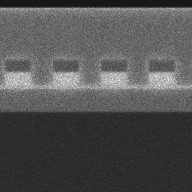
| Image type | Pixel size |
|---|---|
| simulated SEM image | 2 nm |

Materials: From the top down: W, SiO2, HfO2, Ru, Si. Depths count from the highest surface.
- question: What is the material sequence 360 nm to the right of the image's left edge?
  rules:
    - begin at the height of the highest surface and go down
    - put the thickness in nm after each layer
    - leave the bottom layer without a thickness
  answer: W 154, HfO2 8, Ru 46, Si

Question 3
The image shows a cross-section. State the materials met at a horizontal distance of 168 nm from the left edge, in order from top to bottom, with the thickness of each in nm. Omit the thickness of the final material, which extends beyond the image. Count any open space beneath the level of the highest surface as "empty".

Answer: W 154, HfO2 8, Ru 46, Si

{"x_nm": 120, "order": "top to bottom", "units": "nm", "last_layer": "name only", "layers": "W 104, SiO2 24, HfO2 34, Ru 46, Si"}